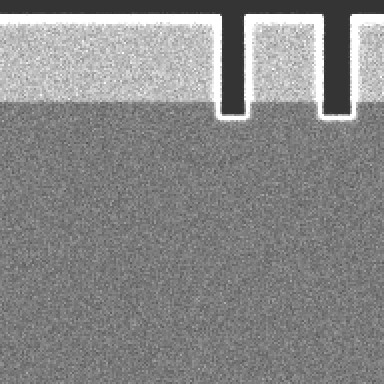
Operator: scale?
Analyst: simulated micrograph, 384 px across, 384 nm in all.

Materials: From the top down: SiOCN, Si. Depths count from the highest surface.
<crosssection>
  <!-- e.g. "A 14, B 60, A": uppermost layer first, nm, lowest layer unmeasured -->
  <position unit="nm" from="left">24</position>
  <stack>SiOCN 86, Si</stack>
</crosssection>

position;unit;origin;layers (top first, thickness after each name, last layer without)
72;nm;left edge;SiOCN 86, Si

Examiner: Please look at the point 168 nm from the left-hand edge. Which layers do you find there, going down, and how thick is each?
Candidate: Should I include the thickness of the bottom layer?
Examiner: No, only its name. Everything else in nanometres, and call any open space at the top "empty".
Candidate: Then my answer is SiOCN 86, Si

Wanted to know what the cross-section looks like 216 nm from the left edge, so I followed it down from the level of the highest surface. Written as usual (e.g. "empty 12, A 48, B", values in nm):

SiOCN 86, Si